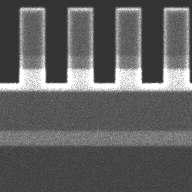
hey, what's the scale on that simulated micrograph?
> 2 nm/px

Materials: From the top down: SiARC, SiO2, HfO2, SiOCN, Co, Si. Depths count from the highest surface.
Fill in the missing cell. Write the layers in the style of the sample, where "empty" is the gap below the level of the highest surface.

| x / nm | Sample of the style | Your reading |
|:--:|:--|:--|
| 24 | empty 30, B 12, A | empty 152, HfO2 14, SiOCN 80, Co 30, Si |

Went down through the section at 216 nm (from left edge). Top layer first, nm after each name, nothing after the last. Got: empty 152, HfO2 14, SiOCN 80, Co 30, Si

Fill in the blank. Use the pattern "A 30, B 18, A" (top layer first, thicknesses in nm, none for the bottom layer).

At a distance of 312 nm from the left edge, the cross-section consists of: empty 152, HfO2 14, SiOCN 80, Co 30, Si